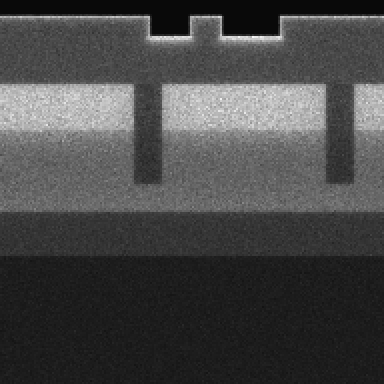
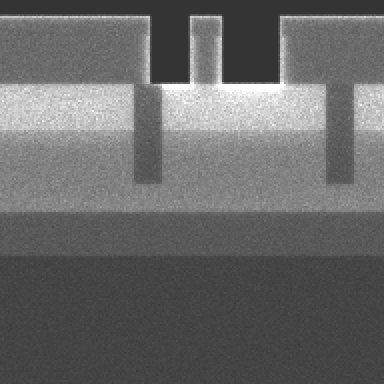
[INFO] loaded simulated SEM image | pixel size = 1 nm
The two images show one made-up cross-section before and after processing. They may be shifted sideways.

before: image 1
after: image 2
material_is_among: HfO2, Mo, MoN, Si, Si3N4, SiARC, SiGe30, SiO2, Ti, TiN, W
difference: SiO2, removed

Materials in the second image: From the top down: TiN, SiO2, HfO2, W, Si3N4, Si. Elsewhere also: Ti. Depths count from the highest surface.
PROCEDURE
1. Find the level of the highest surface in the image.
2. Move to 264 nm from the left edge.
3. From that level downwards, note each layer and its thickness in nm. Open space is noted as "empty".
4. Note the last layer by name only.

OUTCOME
empty 68, HfO2 46, W 82, Si3N4 44, Si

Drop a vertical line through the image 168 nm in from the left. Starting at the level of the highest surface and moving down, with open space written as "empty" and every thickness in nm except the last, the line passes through empty 68, HfO2 46, W 82, Si3N4 44, Si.